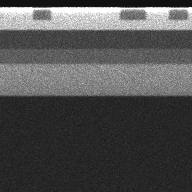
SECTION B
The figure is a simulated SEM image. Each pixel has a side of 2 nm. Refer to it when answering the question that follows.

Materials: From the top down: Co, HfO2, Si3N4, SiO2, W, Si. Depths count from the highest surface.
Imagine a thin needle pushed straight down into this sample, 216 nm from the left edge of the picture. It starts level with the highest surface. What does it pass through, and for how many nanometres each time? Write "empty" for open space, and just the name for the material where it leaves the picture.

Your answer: HfO2 44, Si3N4 38, SiO2 30, W 64, Si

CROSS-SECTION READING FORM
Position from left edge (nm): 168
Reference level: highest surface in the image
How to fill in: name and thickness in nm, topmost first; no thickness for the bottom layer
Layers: HfO2 44, Si3N4 38, SiO2 30, W 64, Si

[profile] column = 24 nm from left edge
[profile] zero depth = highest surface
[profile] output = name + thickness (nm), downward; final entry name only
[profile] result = HfO2 44, Si3N4 38, SiO2 30, W 64, Si